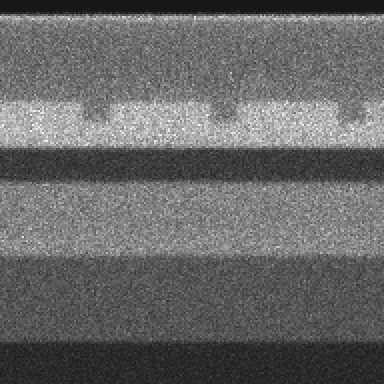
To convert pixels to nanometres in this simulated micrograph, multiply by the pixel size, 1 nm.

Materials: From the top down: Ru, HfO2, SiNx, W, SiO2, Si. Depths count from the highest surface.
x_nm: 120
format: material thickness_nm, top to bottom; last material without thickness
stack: Ru 86, HfO2 46, SiNx 34, W 74, SiO2 86, Si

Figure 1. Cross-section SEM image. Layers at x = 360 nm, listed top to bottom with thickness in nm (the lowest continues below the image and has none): Ru 106, HfO2 26, SiNx 34, W 74, SiO2 86, Si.